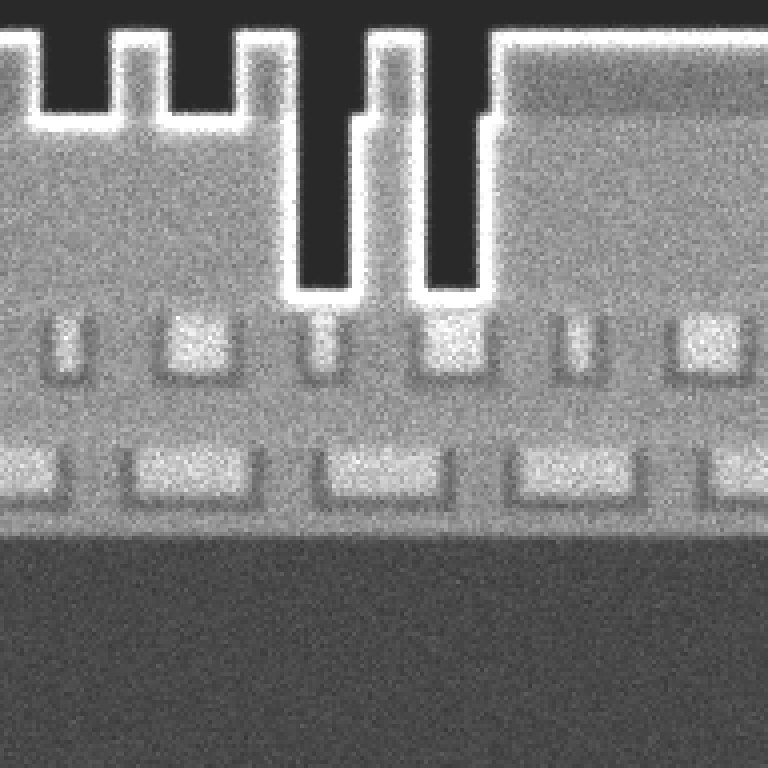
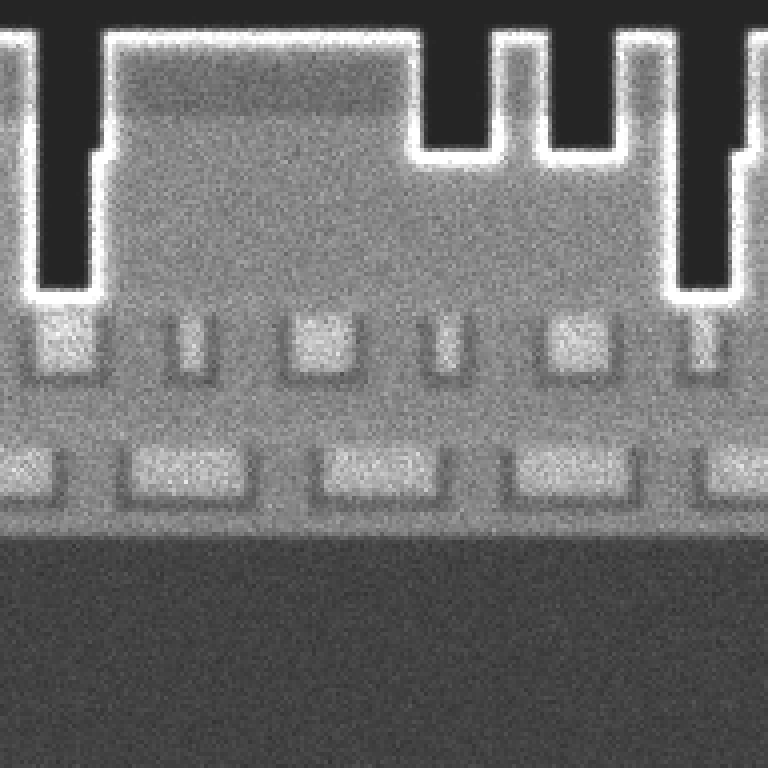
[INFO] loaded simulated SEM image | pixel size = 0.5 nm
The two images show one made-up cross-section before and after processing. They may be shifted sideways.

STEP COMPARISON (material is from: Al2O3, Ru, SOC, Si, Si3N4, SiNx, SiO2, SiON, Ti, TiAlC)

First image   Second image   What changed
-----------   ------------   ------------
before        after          SiO2, removed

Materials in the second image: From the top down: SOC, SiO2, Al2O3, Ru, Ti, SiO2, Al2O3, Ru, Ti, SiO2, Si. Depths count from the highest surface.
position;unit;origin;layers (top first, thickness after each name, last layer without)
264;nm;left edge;SOC 42, SiO2 88, Al2O3 12, SiO2 52, Al2O3 14, Ru 24, Ti 8, SiO2 12, Si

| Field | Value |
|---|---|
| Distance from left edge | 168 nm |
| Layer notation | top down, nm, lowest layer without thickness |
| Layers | SOC 42, SiO2 88, Al2O3 12, Ru 28, Ti 8, SiO2 16, Al2O3 14, Ru 24, Ti 8, SiO2 12, Si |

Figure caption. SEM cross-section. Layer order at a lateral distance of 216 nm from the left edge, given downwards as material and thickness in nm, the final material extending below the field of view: empty 60, SiO2 70, Al2O3 12, Ti 36, SiO2 16, Al2O3 14, Ru 24, Ti 8, SiO2 12, Si